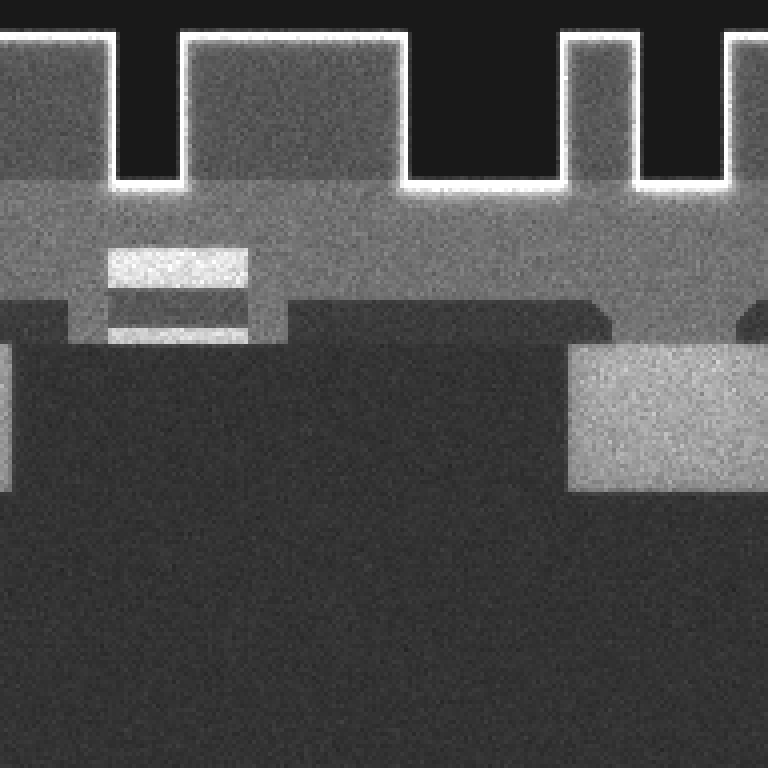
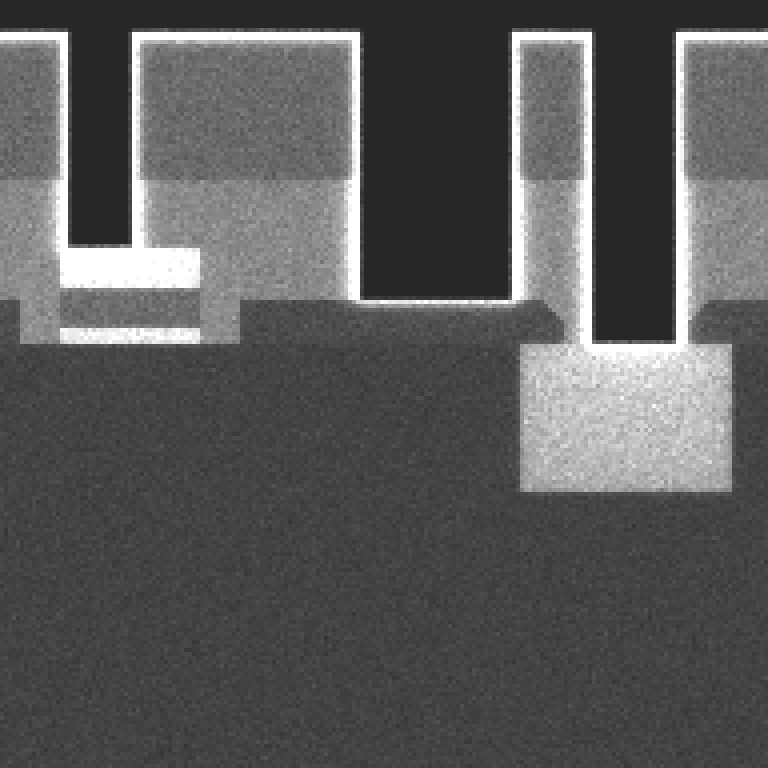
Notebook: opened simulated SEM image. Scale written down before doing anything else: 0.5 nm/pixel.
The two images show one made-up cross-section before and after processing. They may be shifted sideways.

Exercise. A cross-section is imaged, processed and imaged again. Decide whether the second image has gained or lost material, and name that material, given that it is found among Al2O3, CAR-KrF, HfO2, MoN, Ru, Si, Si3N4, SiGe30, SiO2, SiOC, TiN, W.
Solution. removed: SiO2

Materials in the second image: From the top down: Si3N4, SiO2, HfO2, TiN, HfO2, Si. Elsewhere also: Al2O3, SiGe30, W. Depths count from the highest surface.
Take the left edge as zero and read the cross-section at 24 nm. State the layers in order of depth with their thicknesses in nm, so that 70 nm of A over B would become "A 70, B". Si3N4 74, SiO2 34, Al2O3 48, Si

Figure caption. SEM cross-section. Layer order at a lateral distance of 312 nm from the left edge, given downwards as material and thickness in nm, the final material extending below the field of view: empty 156, W 74, Si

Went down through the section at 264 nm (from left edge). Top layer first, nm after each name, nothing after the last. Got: Si3N4 74, SiO2 60, SiGe30 22, W 74, Si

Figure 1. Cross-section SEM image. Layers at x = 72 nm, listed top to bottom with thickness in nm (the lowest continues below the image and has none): Si3N4 74, SiO2 34, HfO2 20, TiN 20, HfO2 8, Si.